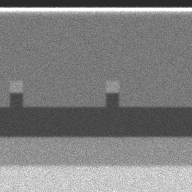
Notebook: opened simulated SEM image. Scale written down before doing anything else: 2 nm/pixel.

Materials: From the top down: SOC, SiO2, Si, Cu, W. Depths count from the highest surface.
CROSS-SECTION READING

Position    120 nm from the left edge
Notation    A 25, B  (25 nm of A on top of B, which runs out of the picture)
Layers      SOC 198, Si 60, Cu 58, W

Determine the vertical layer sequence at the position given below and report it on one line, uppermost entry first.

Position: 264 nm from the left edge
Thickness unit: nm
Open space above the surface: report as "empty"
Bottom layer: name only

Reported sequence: SOC 198, Si 60, Cu 58, W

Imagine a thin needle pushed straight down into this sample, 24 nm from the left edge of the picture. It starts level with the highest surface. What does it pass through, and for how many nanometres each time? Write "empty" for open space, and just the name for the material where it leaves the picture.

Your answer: SOC 146, SiO2 24, Si 88, Cu 58, W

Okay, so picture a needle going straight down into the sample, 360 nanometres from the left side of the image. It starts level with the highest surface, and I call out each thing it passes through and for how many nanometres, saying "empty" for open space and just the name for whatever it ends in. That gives SOC 198, Si 60, Cu 58, W